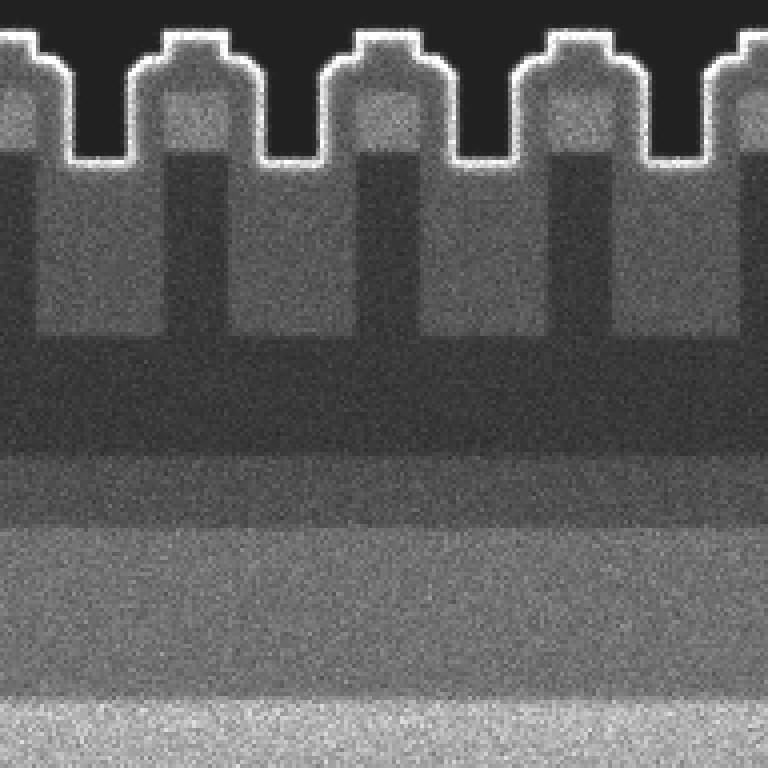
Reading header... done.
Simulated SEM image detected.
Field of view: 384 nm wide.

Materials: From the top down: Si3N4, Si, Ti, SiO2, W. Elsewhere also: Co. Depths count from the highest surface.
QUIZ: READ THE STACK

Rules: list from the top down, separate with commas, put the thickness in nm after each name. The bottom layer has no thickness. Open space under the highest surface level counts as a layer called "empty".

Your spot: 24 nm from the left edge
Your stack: empty 12, Si3N4 140, Si 60, Ti 36, SiO2 86, W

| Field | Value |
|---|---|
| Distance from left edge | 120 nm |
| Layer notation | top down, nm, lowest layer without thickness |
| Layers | empty 12, Si3N4 140, Si 60, Ti 36, SiO2 86, W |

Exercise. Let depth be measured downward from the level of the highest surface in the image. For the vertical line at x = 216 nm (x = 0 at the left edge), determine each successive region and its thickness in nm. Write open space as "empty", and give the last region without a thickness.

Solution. empty 12, Si3N4 140, Si 60, Ti 36, SiO2 86, W